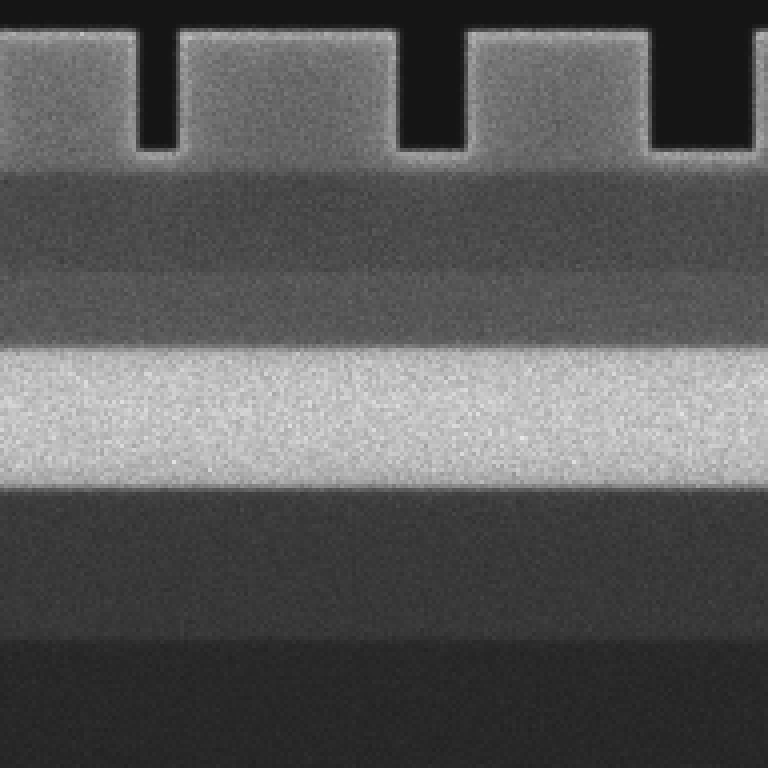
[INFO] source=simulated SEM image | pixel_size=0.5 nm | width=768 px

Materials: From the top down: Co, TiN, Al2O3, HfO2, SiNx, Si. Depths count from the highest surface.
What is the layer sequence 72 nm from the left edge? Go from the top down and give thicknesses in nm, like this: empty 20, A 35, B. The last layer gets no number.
empty 60, Co 10, TiN 50, Al2O3 38, HfO2 70, SiNx 76, Si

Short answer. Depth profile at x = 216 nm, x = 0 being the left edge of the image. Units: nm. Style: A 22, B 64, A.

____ empty 60, Co 10, TiN 50, Al2O3 38, HfO2 70, SiNx 76, Si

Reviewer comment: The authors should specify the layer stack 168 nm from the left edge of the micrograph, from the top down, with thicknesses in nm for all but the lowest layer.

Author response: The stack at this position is Co 70, TiN 50, Al2O3 38, HfO2 70, SiNx 76, Si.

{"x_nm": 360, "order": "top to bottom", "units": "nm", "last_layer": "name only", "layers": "empty 60, Co 10, TiN 50, Al2O3 38, HfO2 70, SiNx 76, Si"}